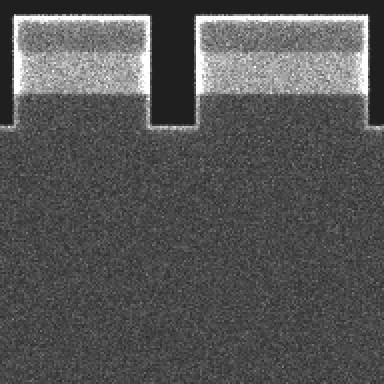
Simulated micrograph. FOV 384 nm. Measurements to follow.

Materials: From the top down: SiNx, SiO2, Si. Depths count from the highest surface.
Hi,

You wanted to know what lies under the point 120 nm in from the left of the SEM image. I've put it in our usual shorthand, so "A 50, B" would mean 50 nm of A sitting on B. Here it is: SiNx 36, SiO2 42, Si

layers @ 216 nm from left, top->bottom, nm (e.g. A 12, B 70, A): SiNx 36, SiO2 42, Si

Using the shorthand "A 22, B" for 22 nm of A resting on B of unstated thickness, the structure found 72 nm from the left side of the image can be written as SiNx 36, SiO2 42, Si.